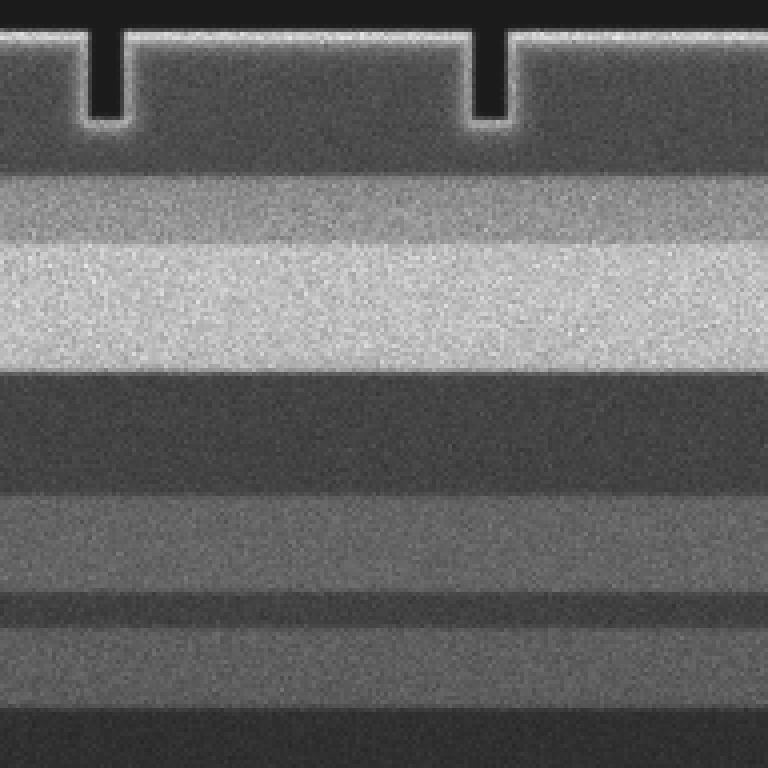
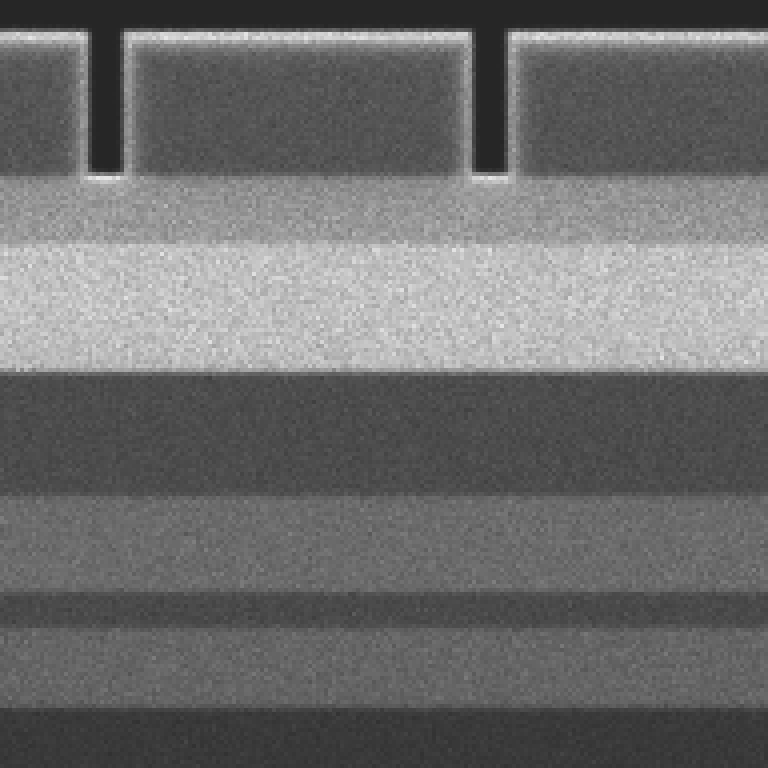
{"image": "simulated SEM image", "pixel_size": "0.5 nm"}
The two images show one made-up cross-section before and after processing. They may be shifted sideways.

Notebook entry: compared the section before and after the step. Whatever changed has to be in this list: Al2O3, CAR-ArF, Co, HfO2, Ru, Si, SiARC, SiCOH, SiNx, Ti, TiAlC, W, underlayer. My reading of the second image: underlayer removed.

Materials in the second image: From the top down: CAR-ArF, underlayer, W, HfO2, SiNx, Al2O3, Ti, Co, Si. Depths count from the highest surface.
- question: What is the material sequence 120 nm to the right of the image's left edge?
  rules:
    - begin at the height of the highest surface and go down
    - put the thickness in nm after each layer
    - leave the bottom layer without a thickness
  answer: CAR-ArF 44, underlayer 28, W 34, HfO2 64, SiNx 62, Al2O3 48, Ti 18, Co 40, Si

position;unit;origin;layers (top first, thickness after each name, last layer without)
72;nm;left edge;CAR-ArF 44, underlayer 28, W 34, HfO2 64, SiNx 62, Al2O3 48, Ti 18, Co 40, Si